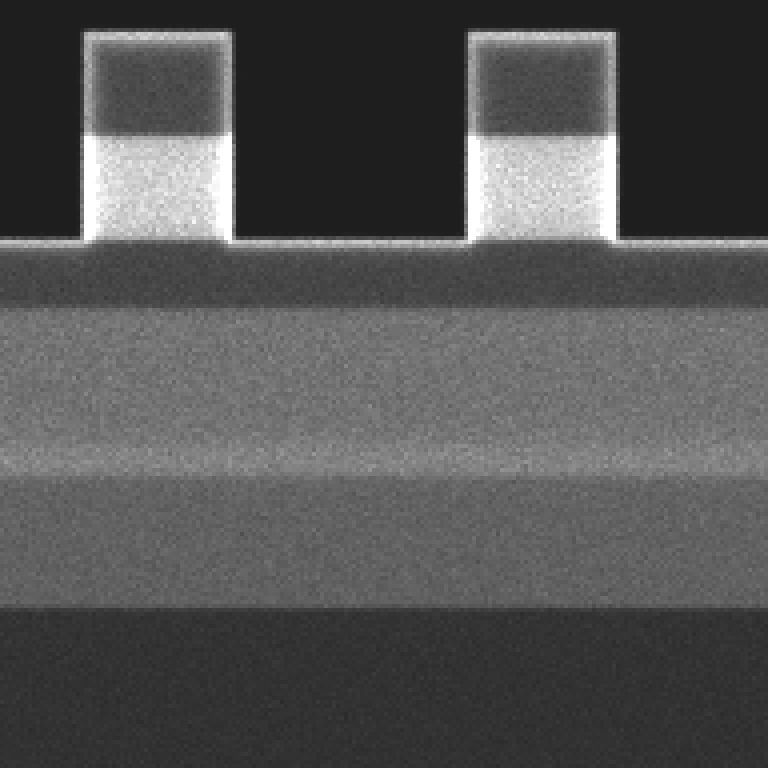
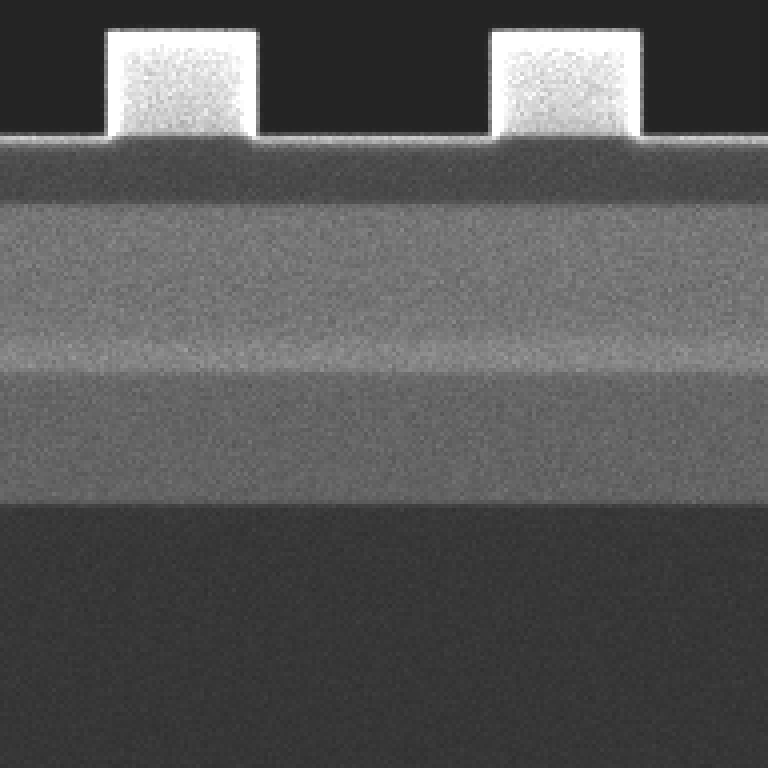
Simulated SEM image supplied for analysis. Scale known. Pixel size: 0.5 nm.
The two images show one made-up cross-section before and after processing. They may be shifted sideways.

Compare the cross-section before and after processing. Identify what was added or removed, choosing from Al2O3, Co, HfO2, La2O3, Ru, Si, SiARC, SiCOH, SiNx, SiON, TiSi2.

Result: SiARC removed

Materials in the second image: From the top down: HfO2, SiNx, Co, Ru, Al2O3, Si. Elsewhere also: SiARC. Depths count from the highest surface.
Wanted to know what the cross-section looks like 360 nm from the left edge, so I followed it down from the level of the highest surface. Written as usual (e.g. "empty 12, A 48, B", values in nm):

empty 52, SiNx 34, Co 68, Ru 16, Al2O3 66, Si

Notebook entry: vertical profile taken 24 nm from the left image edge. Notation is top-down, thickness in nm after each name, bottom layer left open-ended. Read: empty 52, SiNx 34, Co 68, Ru 16, Al2O3 66, Si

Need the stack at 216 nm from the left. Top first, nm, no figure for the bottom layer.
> empty 52, SiNx 34, Co 68, Ru 16, Al2O3 66, Si